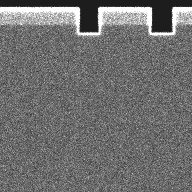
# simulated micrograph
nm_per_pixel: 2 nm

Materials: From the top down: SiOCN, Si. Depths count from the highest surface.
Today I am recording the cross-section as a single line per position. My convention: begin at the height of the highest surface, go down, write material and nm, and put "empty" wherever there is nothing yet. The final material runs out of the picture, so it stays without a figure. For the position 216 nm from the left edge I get SiOCN 34, Si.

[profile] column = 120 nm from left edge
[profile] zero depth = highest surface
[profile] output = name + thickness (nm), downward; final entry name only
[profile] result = SiOCN 34, Si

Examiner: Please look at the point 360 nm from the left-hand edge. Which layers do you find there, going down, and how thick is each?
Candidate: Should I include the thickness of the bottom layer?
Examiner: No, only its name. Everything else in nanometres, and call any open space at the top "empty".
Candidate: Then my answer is SiOCN 34, Si